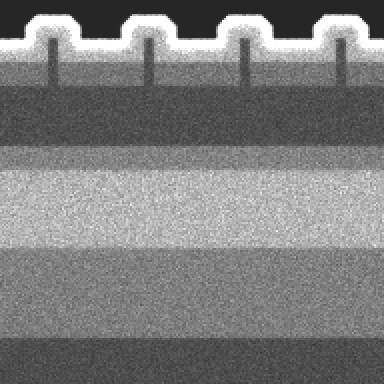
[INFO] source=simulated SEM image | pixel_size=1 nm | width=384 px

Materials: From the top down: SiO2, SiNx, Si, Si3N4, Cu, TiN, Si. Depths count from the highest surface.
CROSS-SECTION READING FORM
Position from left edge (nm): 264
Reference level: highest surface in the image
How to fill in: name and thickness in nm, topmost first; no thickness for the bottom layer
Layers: empty 4, SiO2 42, SiNx 24, Si 60, Si3N4 24, Cu 78, TiN 90, Si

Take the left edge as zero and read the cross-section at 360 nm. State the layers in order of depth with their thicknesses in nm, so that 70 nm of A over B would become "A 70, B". empty 4, SiO2 42, SiNx 24, Si 60, Si3N4 24, Cu 78, TiN 90, Si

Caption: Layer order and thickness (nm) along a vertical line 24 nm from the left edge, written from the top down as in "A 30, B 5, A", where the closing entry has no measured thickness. empty 24, SiO2 22, SiNx 24, Si 60, Si3N4 24, Cu 78, TiN 90, Si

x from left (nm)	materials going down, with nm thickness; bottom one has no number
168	empty 4, SiO2 42, SiNx 24, Si 60, Si3N4 24, Cu 78, TiN 90, Si